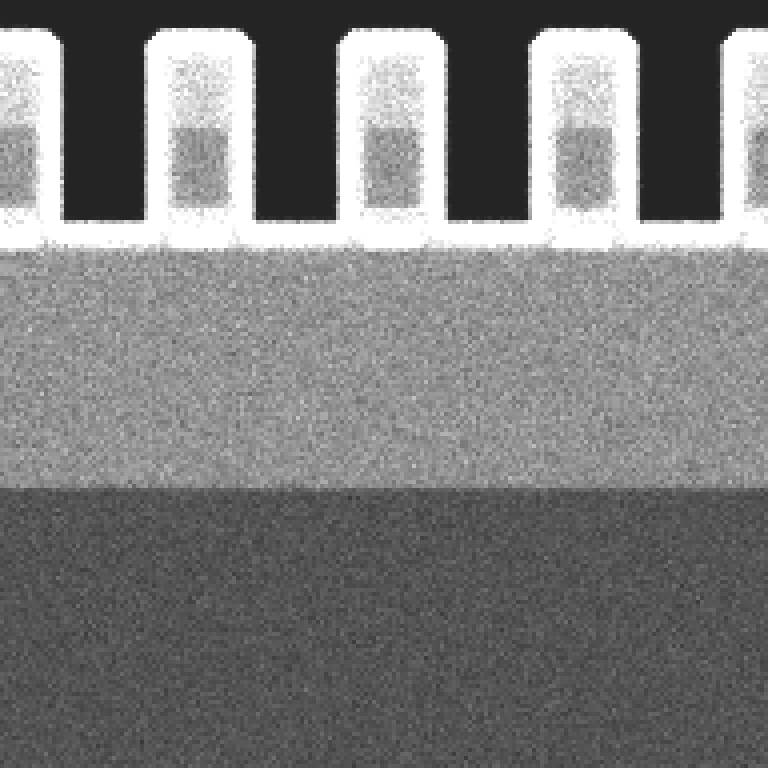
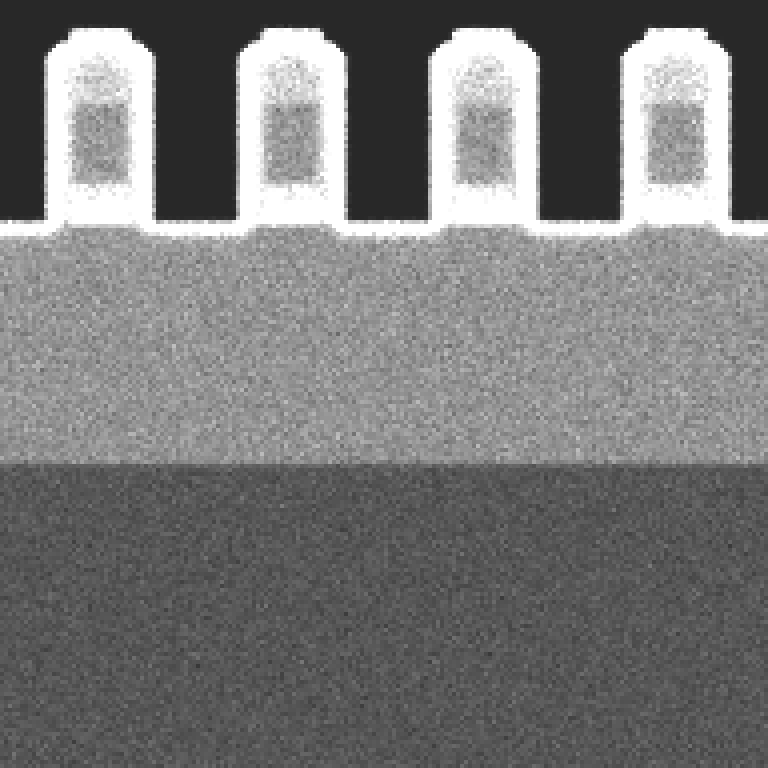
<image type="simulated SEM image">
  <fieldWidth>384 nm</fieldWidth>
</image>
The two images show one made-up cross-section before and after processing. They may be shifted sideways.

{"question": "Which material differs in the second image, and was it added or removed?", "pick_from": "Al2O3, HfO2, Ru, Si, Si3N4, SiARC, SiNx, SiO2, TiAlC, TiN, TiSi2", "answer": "SiO2, removed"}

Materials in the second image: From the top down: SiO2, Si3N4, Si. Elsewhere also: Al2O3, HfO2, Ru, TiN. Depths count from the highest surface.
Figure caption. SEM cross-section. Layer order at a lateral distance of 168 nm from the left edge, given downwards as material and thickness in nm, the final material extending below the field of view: empty 10, SiO2 86, Si3N4 120, Si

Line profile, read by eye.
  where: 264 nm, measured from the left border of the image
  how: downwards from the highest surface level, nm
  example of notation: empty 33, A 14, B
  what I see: empty 10, SiO2 86, Si3N4 120, Si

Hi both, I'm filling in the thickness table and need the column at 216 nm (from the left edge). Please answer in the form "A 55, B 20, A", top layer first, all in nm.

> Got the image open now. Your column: empty 12, SiO2 84, Si3N4 120, Si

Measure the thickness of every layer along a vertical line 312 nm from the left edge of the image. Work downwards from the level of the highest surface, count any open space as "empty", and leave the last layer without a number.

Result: empty 12, SiO2 84, Si3N4 120, Si